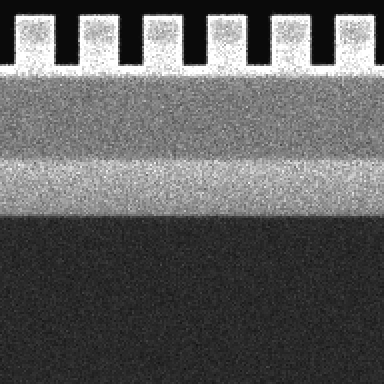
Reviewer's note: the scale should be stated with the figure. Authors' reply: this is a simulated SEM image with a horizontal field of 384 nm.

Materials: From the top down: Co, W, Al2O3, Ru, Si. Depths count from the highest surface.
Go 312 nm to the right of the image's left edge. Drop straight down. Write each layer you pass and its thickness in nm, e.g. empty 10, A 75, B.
empty 50, W 10, Al2O3 84, Ru 56, Si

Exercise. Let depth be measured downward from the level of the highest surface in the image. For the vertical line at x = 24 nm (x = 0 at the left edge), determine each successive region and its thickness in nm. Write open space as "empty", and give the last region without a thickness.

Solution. Co 26, W 34, Al2O3 84, Ru 56, Si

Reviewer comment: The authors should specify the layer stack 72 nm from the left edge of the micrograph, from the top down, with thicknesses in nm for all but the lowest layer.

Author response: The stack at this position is empty 50, W 10, Al2O3 84, Ru 56, Si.